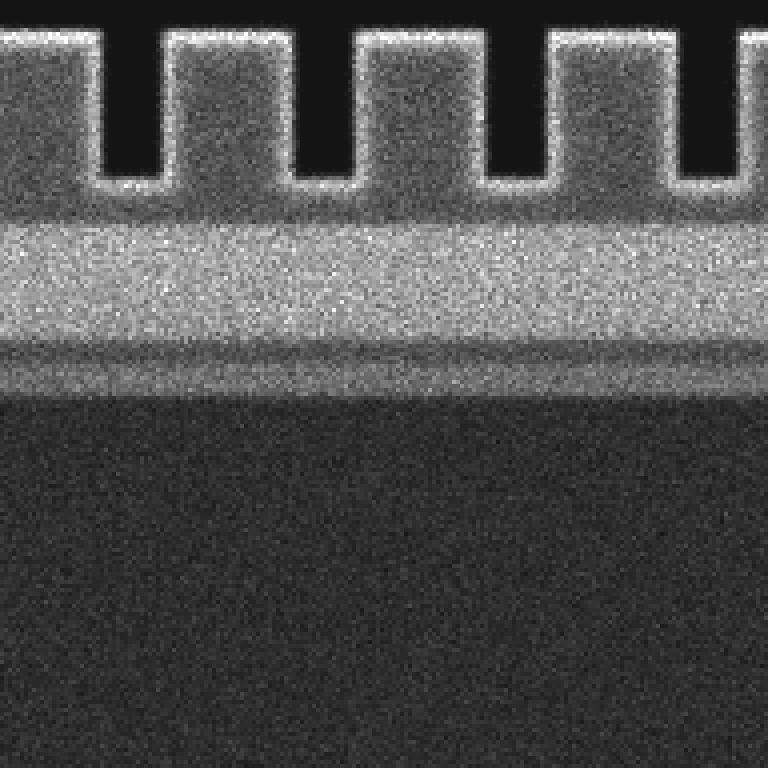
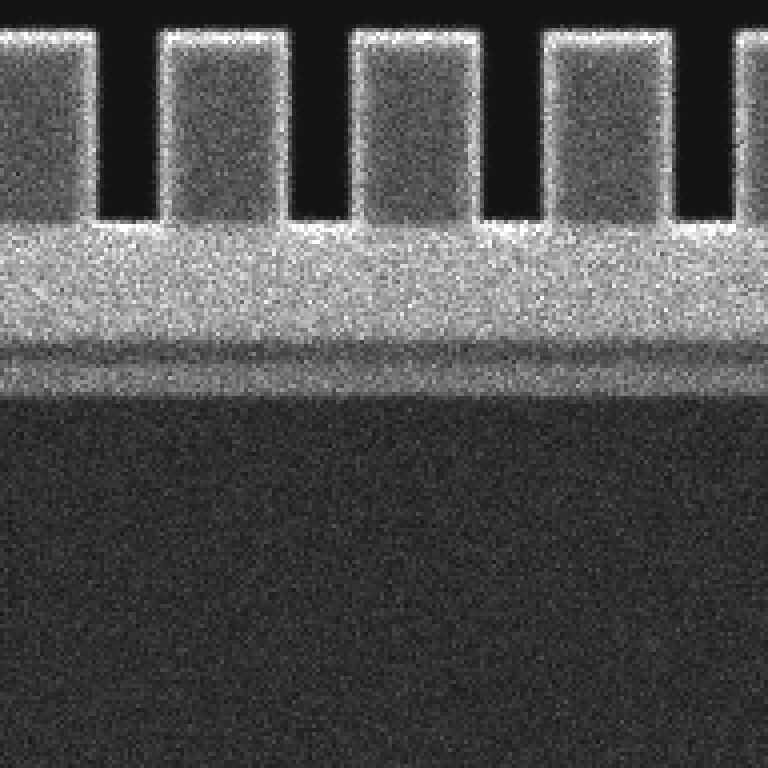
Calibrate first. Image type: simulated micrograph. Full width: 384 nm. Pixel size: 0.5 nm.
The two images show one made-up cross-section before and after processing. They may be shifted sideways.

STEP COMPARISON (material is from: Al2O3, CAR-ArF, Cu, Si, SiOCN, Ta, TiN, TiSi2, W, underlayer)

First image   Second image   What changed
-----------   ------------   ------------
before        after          underlayer, removed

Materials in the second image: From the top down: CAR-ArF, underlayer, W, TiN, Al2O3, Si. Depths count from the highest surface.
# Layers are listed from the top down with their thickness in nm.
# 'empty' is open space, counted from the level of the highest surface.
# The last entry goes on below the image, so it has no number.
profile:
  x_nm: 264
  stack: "empty 96, W 58, TiN 12, Al2O3 16, Si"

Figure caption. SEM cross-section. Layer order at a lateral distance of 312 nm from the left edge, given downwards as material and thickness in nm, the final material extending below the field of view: CAR-ArF 74, underlayer 22, W 58, TiN 12, Al2O3 16, Si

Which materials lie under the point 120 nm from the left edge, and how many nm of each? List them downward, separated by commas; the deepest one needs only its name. CAR-ArF 74, underlayer 22, W 58, TiN 12, Al2O3 16, Si